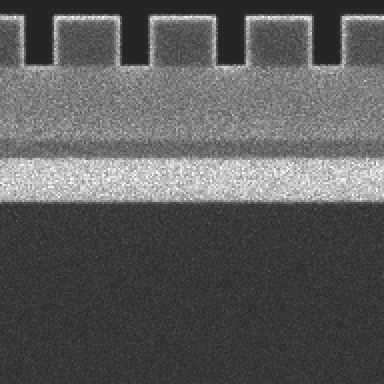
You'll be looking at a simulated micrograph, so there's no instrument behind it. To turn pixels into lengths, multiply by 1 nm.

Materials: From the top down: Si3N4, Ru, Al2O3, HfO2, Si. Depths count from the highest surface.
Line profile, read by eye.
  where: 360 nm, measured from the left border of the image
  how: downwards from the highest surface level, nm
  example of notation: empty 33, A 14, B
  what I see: Si3N4 50, Ru 74, Al2O3 18, HfO2 44, Si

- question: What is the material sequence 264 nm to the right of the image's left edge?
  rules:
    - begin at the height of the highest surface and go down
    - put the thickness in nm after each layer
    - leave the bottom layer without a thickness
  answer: Si3N4 50, Ru 74, Al2O3 18, HfO2 44, Si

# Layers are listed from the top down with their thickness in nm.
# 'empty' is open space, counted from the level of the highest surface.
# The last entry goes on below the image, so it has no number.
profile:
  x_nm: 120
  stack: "empty 50, Ru 74, Al2O3 18, HfO2 44, Si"